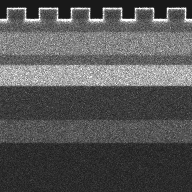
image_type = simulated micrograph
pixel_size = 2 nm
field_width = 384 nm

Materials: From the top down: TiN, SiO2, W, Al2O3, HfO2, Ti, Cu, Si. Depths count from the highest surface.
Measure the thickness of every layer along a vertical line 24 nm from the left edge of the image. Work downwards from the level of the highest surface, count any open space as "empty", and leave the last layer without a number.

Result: TiN 22, SiO2 26, W 46, Al2O3 20, HfO2 42, Ti 68, Cu 46, Si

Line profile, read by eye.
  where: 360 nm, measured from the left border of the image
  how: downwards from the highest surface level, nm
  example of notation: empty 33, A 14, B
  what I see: TiN 22, SiO2 26, W 46, Al2O3 20, HfO2 42, Ti 68, Cu 46, Si